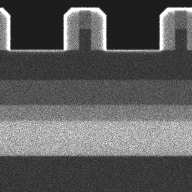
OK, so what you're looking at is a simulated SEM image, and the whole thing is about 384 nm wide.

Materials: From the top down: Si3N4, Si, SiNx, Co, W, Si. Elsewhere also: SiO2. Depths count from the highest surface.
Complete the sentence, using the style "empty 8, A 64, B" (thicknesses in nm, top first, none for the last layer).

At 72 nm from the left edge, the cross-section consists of empty 84, Si 60, SiNx 50, Co 32, W 70, Si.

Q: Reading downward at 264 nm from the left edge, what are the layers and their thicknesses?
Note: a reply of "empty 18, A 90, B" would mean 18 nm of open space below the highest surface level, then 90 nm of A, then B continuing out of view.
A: empty 84, Si 60, SiNx 50, Co 32, W 70, Si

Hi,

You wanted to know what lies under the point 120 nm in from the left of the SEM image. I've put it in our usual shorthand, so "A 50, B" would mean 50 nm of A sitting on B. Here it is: empty 84, Si 60, SiNx 50, Co 32, W 70, Si